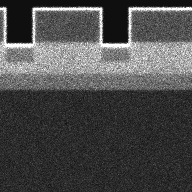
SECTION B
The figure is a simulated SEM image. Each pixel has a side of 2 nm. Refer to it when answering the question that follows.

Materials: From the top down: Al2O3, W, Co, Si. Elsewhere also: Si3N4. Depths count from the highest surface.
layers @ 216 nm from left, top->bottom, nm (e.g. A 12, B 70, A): empty 72, Al2O3 36, W 24, Co 32, Si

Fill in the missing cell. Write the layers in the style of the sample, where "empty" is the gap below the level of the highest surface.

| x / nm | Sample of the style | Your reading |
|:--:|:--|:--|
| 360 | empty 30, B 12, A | Si3N4 68, W 64, Co 32, Si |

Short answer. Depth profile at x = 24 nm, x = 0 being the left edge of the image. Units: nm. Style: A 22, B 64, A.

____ empty 72, Al2O3 36, W 24, Co 32, Si